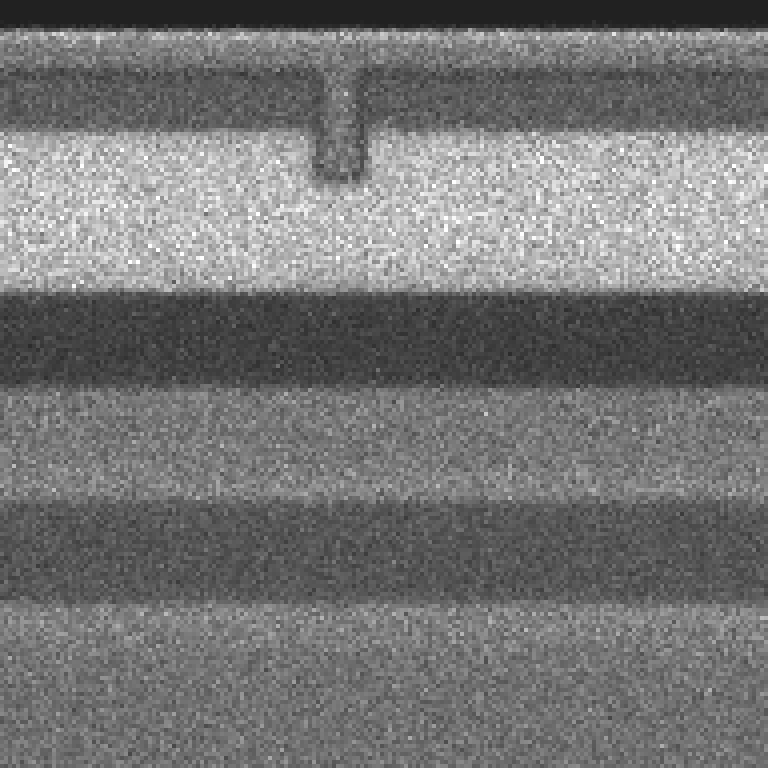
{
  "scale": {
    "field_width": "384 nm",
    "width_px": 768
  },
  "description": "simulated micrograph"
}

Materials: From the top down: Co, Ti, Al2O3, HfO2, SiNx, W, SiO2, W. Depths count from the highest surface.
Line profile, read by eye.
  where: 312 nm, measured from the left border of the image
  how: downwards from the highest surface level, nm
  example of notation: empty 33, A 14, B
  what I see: Co 18, Ti 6, Al2O3 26, HfO2 80, SiNx 48, W 56, SiO2 52, W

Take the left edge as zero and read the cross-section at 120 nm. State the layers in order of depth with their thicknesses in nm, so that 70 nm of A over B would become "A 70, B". Co 18, Ti 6, Al2O3 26, HfO2 80, SiNx 48, W 56, SiO2 52, W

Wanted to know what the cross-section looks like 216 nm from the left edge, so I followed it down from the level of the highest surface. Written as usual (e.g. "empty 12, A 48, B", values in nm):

Co 18, Ti 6, Al2O3 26, HfO2 80, SiNx 48, W 56, SiO2 52, W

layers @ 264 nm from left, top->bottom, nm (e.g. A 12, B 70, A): Co 18, Ti 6, Al2O3 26, HfO2 80, SiNx 48, W 56, SiO2 52, W